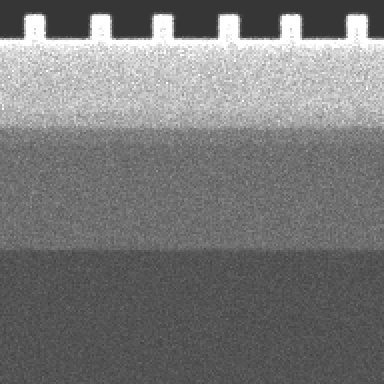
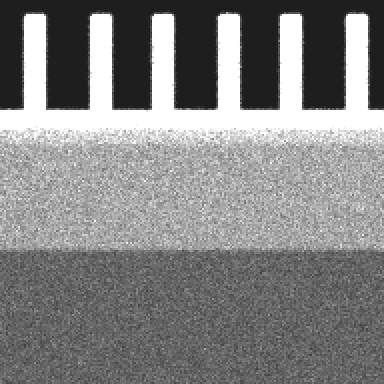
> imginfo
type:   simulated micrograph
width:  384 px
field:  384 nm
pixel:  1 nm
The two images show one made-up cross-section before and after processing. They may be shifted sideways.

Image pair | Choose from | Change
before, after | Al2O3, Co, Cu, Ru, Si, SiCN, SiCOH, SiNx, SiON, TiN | Ru (removed)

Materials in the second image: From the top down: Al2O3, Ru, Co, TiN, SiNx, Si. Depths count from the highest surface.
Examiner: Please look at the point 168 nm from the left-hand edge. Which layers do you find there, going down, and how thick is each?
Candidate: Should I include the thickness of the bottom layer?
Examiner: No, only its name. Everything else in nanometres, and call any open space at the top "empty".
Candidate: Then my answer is Al2O3 24, Ru 72, Co 16, TiN 16, SiNx 106, Si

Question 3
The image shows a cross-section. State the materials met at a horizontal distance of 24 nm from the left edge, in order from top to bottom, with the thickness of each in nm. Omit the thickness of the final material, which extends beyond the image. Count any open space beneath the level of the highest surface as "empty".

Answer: empty 96, Co 16, TiN 16, SiNx 106, Si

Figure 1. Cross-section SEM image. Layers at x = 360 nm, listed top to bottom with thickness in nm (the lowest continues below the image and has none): Al2O3 24, Ru 72, Co 16, TiN 16, SiNx 106, Si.